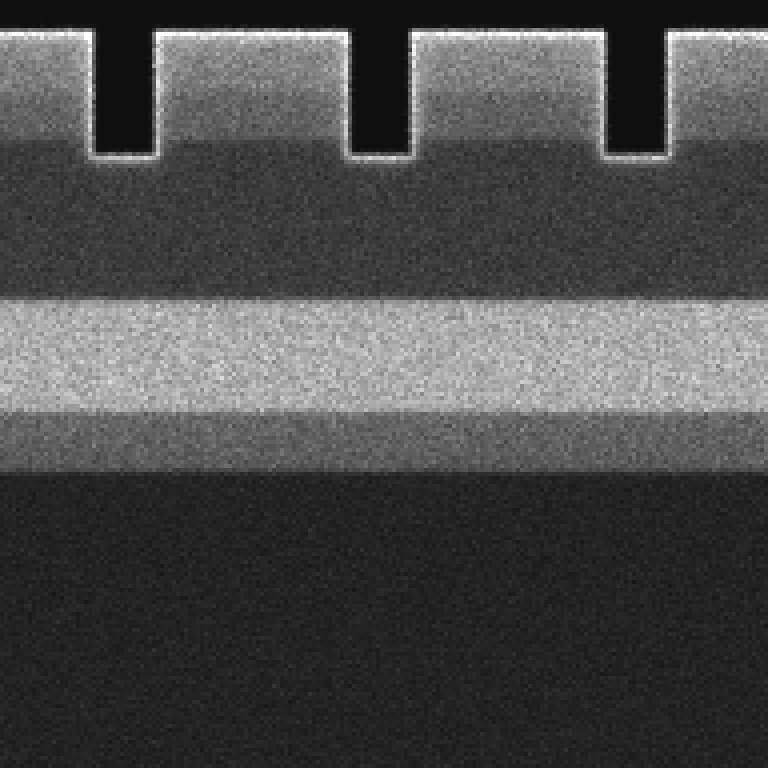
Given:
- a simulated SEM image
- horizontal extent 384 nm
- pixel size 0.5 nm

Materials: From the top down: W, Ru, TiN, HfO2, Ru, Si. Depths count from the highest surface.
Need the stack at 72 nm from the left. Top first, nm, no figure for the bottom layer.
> empty 62, TiN 72, HfO2 56, Ru 30, Si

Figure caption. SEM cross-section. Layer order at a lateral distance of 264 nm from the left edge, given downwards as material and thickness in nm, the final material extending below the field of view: W 30, Ru 24, TiN 80, HfO2 56, Ru 30, Si